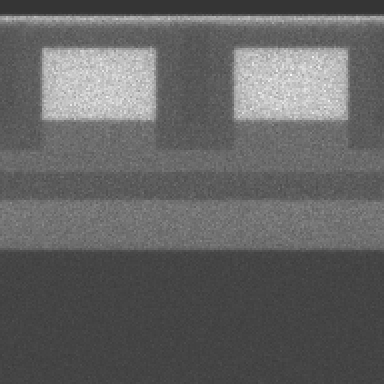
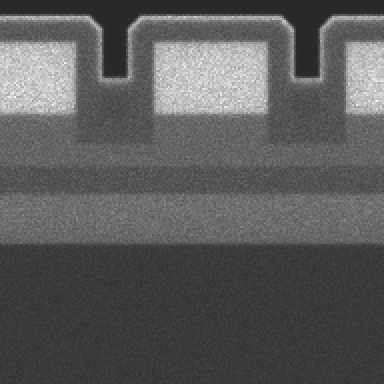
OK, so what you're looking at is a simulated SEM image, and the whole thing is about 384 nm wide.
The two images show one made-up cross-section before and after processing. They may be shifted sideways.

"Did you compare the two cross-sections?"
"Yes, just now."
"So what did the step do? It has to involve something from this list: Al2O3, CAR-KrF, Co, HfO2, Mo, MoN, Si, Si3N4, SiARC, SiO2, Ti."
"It removed SiARC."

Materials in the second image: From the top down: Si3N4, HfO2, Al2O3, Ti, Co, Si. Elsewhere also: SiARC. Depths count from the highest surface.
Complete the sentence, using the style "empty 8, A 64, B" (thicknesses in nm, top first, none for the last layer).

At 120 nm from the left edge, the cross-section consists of empty 62, SiARC 40, Si3N4 26, Al2O3 22, Ti 28, Co 50, Si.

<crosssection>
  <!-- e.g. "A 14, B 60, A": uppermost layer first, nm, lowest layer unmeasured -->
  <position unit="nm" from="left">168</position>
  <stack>Si3N4 26, HfO2 72, Al2O3 52, Ti 28, Co 50, Si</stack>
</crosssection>